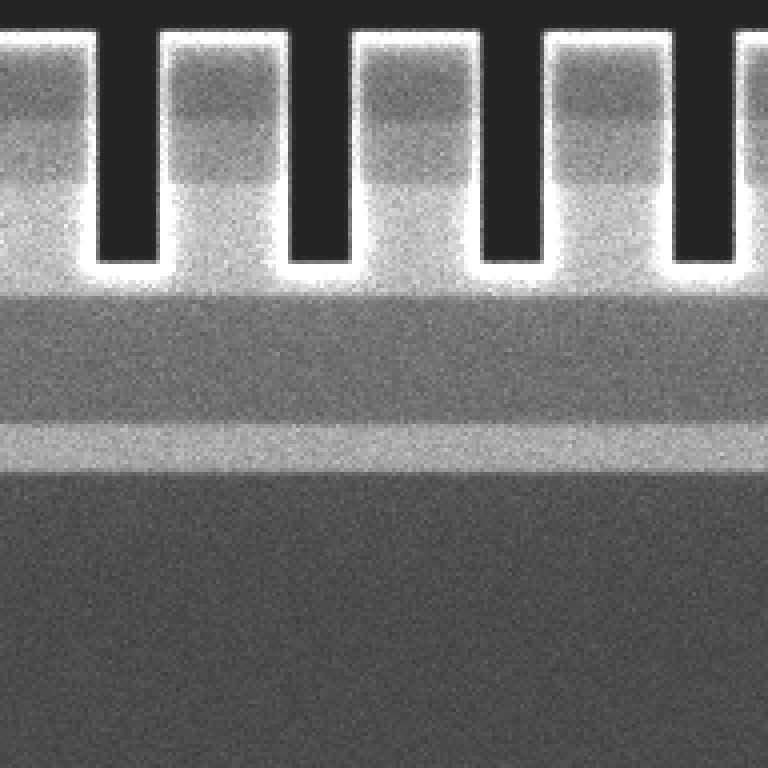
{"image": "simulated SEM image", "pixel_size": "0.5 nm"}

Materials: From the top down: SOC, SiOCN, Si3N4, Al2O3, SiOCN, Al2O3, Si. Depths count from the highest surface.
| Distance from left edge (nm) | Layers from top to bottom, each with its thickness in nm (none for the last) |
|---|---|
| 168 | empty 116, Al2O3 16, SiOCN 64, Al2O3 24, Si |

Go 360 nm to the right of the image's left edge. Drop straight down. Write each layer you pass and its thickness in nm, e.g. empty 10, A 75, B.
empty 116, Al2O3 16, SiOCN 64, Al2O3 24, Si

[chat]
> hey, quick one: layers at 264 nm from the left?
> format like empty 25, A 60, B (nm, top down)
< empty 116, Al2O3 16, SiOCN 64, Al2O3 24, Si